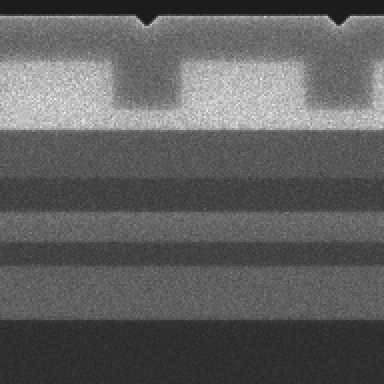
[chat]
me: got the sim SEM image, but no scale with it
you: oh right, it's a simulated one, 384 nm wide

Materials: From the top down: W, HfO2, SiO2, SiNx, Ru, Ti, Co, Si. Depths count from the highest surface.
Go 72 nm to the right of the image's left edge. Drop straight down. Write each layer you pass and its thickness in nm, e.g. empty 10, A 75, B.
W 46, HfO2 68, SiO2 48, SiNx 34, Ru 30, Ti 24, Co 54, Si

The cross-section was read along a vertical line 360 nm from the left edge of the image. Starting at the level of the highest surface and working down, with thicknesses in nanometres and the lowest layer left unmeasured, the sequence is W 94, HfO2 20, SiO2 48, SiNx 34, Ru 30, Ti 24, Co 54, Si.